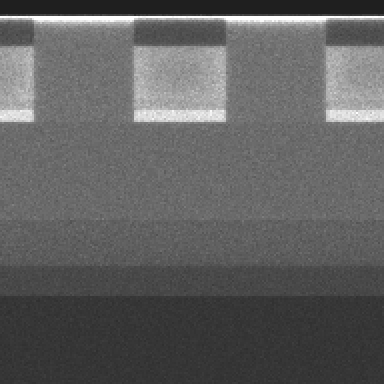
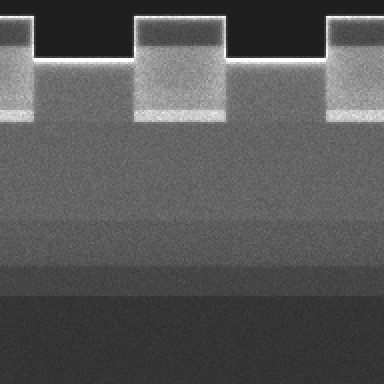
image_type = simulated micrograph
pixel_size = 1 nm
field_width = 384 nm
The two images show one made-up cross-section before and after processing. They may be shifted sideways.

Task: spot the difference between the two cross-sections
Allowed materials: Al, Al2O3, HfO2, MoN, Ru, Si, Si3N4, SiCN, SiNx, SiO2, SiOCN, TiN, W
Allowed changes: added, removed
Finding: removed Al2O3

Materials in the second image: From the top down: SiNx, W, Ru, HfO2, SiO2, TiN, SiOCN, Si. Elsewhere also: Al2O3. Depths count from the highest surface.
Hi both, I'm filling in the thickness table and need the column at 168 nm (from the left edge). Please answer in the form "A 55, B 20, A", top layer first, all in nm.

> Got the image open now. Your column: SiNx 30, W 54, Ru 10, HfO2 12, SiO2 98, TiN 46, SiOCN 30, Si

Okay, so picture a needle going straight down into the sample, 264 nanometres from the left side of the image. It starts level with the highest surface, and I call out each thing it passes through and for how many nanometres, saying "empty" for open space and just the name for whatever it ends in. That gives empty 42, Al2O3 64, SiO2 98, TiN 46, SiOCN 30, Si